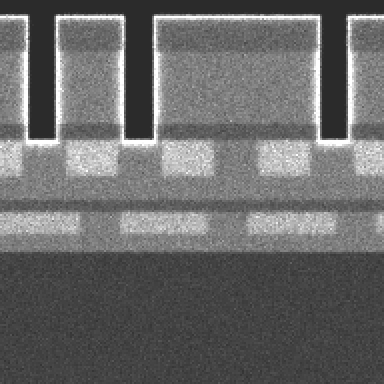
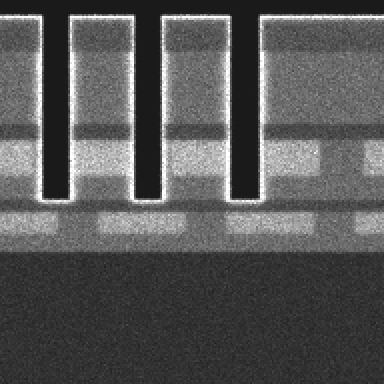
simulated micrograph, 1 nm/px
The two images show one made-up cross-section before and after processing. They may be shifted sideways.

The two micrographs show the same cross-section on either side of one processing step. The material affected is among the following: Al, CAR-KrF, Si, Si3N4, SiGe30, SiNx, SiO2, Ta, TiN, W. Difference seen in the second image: SiO2 removed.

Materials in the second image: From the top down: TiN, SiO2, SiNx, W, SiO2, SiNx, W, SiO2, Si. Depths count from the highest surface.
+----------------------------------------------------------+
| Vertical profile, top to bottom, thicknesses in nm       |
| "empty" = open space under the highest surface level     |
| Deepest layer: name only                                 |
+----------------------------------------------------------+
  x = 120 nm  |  TiN 36, SiO2 72, SiNx 16, W 36, SiO2 24, SiNx 12, W 22, SiO2 18, Si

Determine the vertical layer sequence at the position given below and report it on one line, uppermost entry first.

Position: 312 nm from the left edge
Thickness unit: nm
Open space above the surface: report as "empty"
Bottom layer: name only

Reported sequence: TiN 36, SiO2 72, SiNx 16, W 36, SiO2 24, SiNx 12, W 22, SiO2 18, Si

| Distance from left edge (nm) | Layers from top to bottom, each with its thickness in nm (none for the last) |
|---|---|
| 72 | TiN 36, SiO2 72, SiNx 16, SiO2 60, SiNx 12, SiO2 40, Si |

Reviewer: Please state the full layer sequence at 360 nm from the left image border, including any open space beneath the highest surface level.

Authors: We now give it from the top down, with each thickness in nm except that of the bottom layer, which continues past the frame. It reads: TiN 36, SiO2 72, SiNx 16, SiO2 60, SiNx 12, W 22, SiO2 18, Si